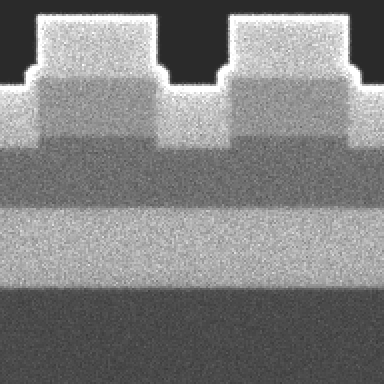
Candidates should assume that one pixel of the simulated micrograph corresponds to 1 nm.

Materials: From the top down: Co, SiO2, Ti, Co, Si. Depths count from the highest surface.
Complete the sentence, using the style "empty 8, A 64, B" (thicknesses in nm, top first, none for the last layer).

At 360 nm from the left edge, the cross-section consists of empty 70, Co 62, Ti 60, Co 80, Si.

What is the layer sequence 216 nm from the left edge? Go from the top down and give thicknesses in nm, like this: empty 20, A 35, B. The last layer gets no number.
empty 70, Co 62, Ti 60, Co 80, Si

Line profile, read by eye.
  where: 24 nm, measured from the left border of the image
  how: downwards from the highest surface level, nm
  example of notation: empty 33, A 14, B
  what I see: empty 70, Co 62, Ti 60, Co 80, Si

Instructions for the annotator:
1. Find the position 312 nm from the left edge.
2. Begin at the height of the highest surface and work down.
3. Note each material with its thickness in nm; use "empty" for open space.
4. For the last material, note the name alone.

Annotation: Co 62, SiO2 58, Ti 72, Co 80, Si